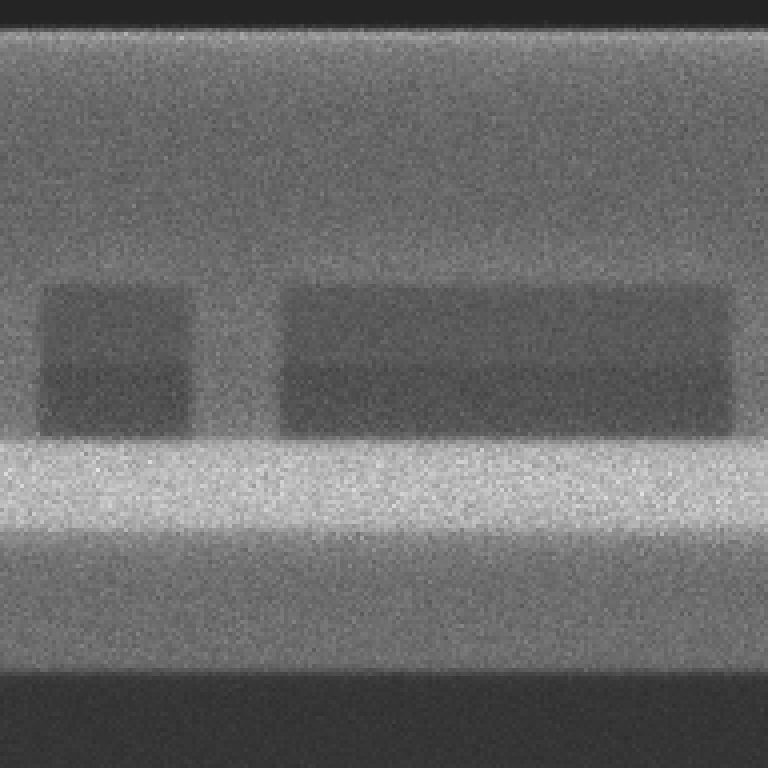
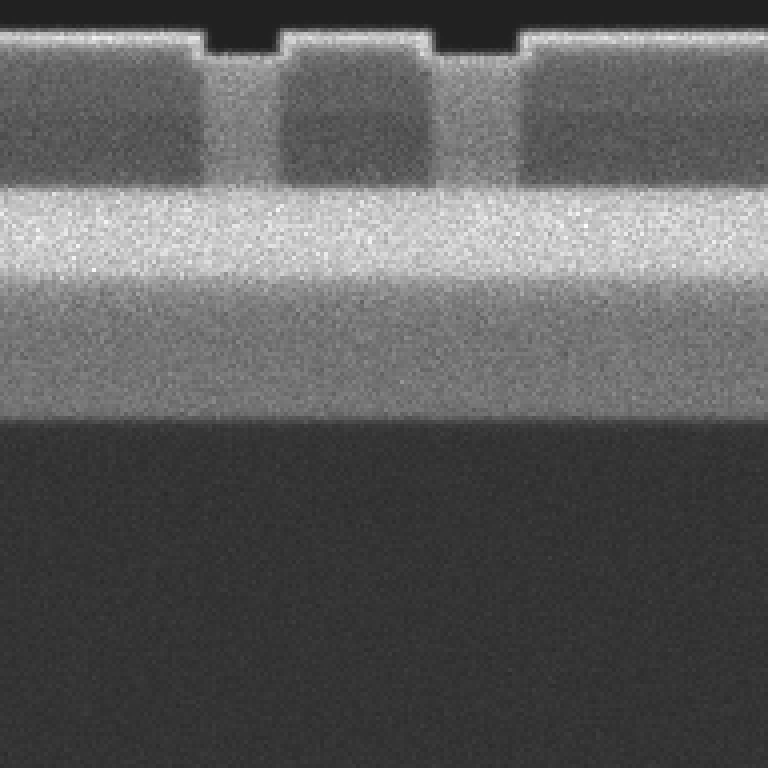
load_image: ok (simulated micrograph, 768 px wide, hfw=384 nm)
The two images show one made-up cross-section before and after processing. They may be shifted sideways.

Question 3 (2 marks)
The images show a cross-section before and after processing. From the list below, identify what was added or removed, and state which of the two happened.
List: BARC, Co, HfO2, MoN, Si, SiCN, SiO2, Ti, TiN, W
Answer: Co was removed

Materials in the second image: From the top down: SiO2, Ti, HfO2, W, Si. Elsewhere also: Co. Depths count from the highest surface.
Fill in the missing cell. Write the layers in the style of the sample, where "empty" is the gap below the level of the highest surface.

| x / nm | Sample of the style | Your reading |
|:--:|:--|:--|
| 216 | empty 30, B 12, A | empty 12, Co 66, HfO2 44, W 72, Si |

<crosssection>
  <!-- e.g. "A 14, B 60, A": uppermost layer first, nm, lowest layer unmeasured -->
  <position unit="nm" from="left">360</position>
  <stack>SiO2 40, Ti 38, HfO2 44, W 72, Si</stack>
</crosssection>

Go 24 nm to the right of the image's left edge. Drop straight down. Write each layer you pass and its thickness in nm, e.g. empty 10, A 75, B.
SiO2 40, Ti 38, HfO2 44, W 72, Si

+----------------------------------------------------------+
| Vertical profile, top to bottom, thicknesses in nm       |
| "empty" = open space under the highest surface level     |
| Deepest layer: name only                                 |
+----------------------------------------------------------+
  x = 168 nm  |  SiO2 40, Ti 38, HfO2 44, W 72, Si